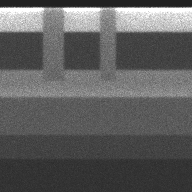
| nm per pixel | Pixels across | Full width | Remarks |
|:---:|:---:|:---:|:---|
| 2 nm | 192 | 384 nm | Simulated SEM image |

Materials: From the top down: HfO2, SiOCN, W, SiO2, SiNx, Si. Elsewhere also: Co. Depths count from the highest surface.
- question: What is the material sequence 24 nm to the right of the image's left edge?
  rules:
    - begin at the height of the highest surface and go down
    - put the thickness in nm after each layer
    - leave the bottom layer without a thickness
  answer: HfO2 48, SiOCN 76, W 54, SiO2 76, SiNx 48, Si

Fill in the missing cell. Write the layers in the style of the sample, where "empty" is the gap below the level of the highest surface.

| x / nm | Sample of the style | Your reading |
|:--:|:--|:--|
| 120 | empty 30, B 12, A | Co 146, W 32, SiO2 76, SiNx 48, Si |